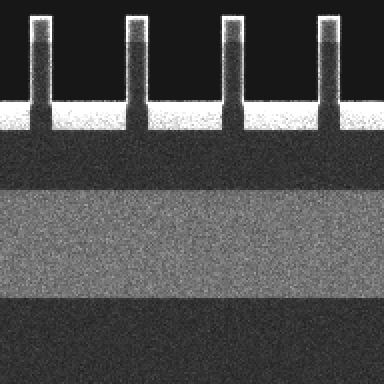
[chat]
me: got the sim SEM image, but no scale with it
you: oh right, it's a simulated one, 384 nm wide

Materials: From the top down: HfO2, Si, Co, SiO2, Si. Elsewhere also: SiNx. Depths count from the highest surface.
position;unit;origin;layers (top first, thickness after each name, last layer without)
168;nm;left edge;empty 86, HfO2 28, Si 60, Co 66, SiO2 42, Si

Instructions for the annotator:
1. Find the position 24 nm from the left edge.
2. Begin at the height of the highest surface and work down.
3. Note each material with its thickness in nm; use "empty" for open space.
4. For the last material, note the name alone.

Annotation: empty 86, HfO2 28, Si 60, Co 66, SiO2 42, Si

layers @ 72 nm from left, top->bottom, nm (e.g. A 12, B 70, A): empty 86, HfO2 28, Si 60, Co 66, SiO2 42, Si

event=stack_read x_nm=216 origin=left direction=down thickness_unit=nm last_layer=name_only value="empty 86, HfO2 28, Si 60, Co 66, SiO2 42, Si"